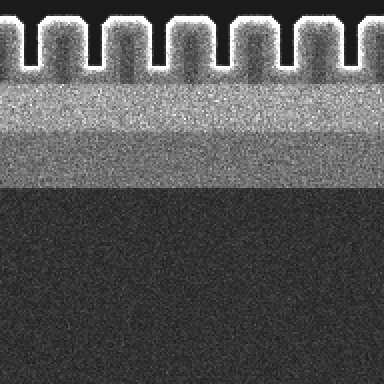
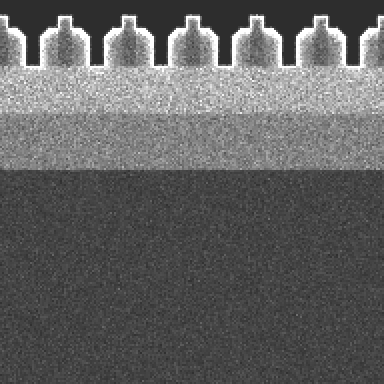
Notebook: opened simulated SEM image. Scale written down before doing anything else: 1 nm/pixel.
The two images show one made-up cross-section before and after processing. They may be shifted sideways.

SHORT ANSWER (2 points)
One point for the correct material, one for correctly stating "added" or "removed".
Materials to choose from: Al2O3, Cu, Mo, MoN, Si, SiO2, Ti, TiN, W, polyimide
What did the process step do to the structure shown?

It removed SiO2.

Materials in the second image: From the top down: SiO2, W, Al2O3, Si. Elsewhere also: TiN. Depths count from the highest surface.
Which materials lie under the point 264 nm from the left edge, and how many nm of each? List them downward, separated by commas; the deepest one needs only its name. empty 12, SiO2 38, W 48, Al2O3 56, Si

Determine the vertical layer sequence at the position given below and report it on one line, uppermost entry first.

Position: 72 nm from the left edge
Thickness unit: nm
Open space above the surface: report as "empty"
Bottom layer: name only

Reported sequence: empty 12, SiO2 38, W 48, Al2O3 56, Si